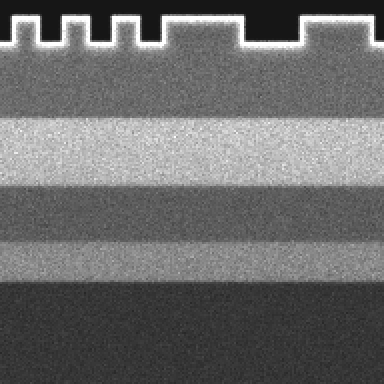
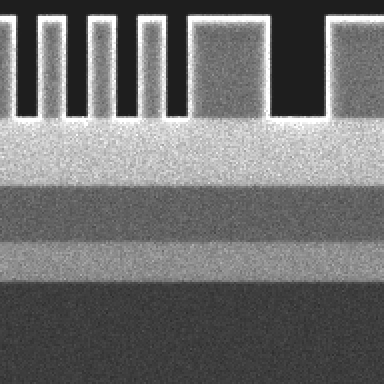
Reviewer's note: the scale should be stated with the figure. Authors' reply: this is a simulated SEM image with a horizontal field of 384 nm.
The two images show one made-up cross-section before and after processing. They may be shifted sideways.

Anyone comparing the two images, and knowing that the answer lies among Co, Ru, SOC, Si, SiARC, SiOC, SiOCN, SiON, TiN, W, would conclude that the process removed SOC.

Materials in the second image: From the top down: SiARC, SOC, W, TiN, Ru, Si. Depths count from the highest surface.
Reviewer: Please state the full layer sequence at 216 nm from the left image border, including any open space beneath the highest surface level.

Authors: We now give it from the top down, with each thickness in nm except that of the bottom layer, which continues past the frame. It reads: SiARC 26, SOC 76, W 68, TiN 56, Ru 40, Si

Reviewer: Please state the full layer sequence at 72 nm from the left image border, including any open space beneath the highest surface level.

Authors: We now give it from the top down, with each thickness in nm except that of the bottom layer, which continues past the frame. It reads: empty 102, W 68, TiN 56, Ru 40, Si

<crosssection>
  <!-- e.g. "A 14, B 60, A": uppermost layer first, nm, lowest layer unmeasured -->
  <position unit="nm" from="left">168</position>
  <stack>empty 102, W 68, TiN 56, Ru 40, Si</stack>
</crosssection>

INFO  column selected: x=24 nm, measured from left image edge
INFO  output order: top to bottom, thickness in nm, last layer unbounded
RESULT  empty 102, W 68, TiN 56, Ru 40, Si